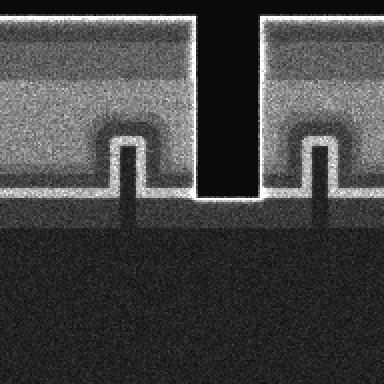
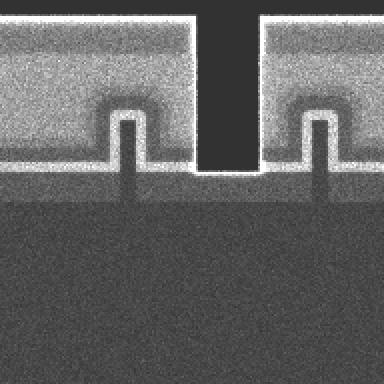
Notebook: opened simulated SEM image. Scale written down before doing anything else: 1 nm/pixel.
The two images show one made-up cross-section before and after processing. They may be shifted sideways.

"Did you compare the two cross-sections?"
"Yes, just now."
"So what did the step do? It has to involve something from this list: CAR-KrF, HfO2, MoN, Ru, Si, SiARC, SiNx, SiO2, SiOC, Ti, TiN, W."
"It removed SiARC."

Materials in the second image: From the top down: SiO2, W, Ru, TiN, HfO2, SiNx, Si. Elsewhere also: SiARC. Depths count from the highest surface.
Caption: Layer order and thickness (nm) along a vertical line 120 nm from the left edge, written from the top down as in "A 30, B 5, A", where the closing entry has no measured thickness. SiO2 38, W 32, Ru 10, TiN 14, HfO2 10, Si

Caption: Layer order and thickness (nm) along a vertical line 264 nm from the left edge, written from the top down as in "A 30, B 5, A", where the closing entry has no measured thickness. SiO2 38, W 84, Ru 10, TiN 14, HfO2 10, SiNx 30, Si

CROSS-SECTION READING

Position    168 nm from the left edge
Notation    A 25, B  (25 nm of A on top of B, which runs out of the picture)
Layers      SiO2 38, W 46, Ru 48, TiN 14, HfO2 10, SiNx 30, Si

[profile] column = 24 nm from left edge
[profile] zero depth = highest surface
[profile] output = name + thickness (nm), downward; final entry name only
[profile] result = SiO2 38, W 84, Ru 10, TiN 14, HfO2 10, SiNx 30, Si